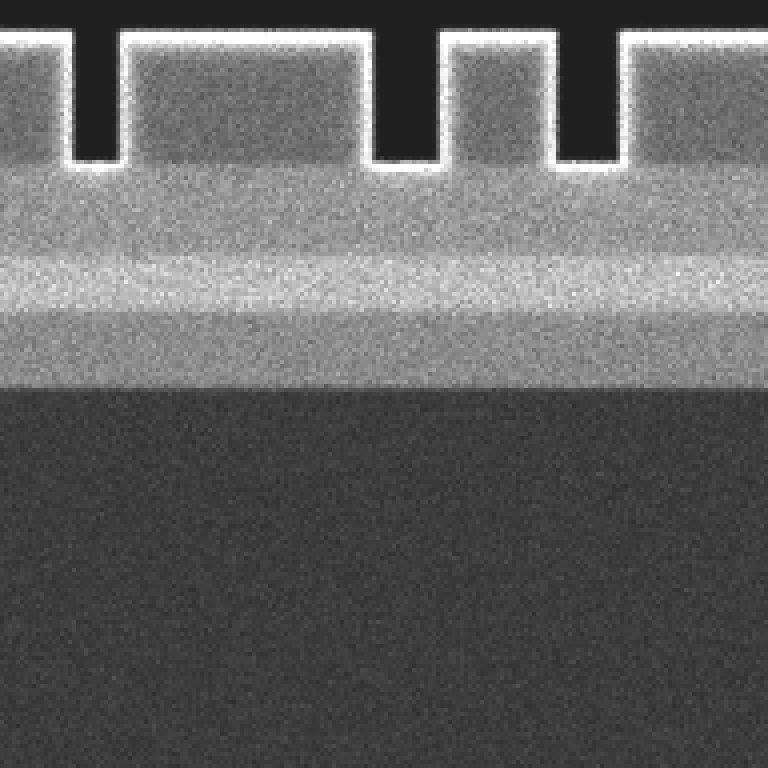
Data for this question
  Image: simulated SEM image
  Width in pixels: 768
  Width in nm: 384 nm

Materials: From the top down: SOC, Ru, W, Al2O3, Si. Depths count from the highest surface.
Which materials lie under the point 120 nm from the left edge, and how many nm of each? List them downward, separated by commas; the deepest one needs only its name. SOC 66, Ru 46, W 28, Al2O3 38, Si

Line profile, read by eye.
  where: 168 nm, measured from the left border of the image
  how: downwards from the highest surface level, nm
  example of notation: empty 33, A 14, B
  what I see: SOC 66, Ru 46, W 28, Al2O3 38, Si